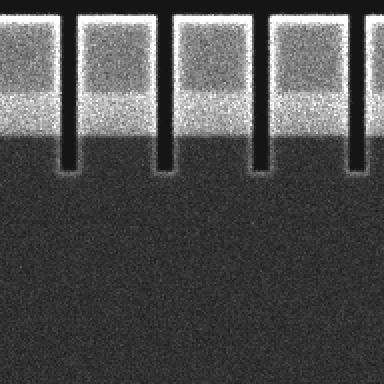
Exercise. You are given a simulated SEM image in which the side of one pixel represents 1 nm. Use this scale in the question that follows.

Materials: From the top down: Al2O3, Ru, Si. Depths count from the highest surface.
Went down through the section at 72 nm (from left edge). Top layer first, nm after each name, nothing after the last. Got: empty 156, Si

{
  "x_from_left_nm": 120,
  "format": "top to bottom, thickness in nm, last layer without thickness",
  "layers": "Al2O3 76, Ru 44, Si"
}